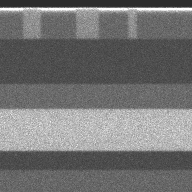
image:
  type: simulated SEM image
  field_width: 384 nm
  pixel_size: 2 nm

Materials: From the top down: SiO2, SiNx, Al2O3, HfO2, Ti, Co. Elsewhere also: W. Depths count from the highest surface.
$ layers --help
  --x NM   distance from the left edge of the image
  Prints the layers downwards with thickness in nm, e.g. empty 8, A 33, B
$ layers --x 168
W 62, SiNx 90, Al2O3 50, HfO2 84, Ti 38, Co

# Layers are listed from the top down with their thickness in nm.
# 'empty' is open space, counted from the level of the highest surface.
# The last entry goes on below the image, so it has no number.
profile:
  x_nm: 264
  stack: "W 62, SiNx 90, Al2O3 50, HfO2 84, Ti 38, Co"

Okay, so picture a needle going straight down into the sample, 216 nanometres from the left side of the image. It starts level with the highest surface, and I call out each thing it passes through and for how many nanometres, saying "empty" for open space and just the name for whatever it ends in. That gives SiO2 62, SiNx 90, Al2O3 50, HfO2 84, Ti 38, Co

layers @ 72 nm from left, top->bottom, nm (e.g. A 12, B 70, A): W 62, SiNx 90, Al2O3 50, HfO2 84, Ti 38, Co